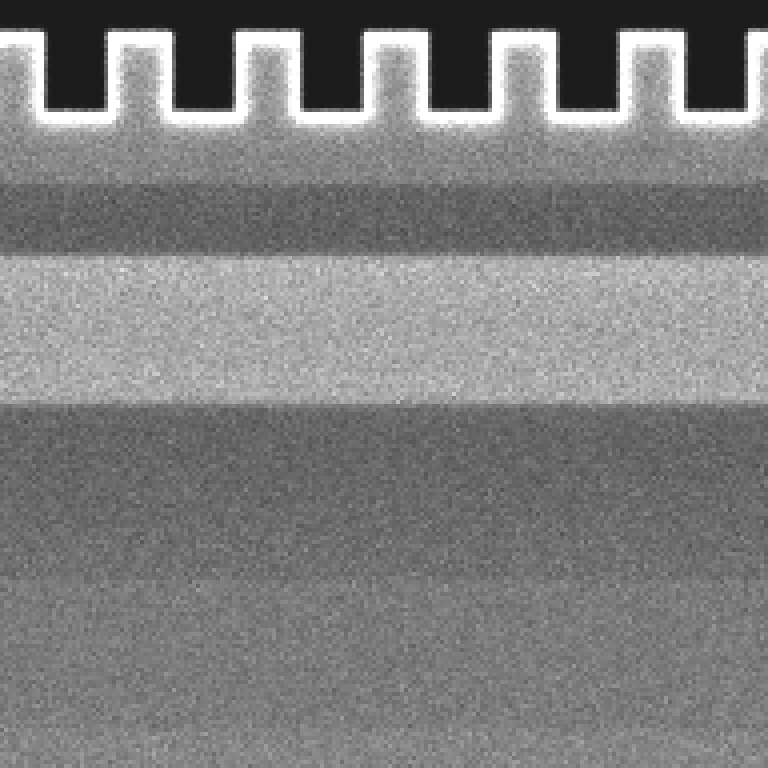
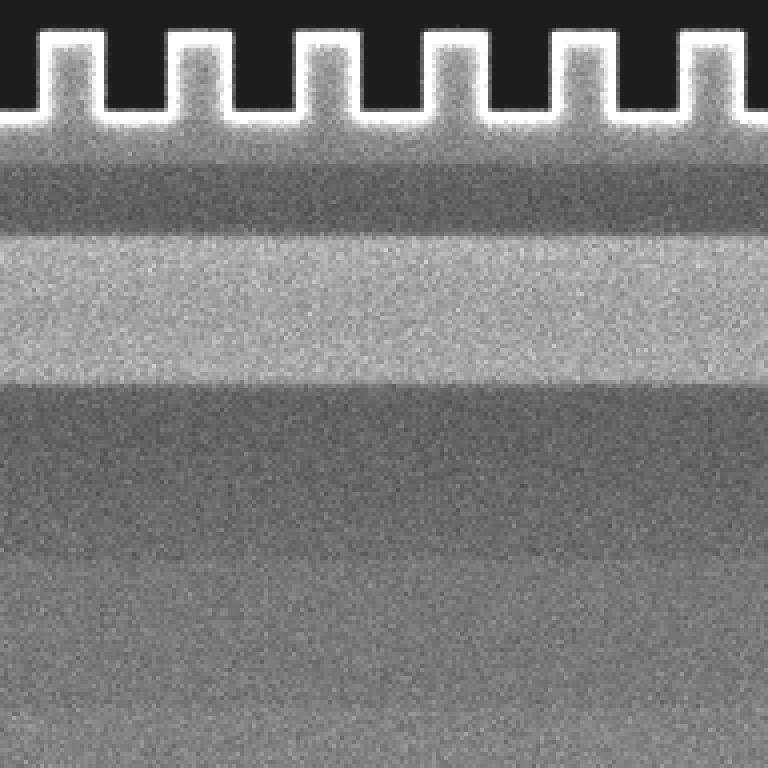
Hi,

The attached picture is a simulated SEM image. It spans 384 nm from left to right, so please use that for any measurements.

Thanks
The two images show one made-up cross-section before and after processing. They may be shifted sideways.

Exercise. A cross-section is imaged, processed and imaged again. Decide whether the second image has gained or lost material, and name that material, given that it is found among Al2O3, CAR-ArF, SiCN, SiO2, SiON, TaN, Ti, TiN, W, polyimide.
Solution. removed: Al2O3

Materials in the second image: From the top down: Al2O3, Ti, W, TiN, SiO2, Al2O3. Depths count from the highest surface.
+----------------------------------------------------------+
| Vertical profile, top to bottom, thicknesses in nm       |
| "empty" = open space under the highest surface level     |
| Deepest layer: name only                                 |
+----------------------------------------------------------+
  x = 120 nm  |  empty 40, Al2O3 26, Ti 36, W 74, TiN 88, SiO2 74, Al2O3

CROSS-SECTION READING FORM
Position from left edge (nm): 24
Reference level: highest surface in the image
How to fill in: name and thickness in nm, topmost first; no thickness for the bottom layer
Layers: Al2O3 66, Ti 36, W 74, TiN 88, SiO2 74, Al2O3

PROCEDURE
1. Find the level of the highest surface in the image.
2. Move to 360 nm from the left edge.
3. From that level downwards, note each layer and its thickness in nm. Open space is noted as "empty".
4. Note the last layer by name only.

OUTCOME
Al2O3 66, Ti 36, W 74, TiN 88, SiO2 74, Al2O3